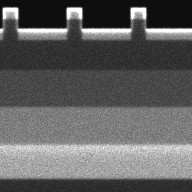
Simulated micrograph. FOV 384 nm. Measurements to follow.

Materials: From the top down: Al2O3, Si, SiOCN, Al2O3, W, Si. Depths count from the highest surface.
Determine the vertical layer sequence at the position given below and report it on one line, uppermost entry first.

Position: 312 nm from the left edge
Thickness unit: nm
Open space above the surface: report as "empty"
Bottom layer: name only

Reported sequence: empty 42, Al2O3 22, Si 60, SiOCN 74, Al2O3 76, W 68, Si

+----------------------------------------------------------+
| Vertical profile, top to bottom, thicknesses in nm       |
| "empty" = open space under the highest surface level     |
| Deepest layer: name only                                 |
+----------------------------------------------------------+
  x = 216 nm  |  empty 42, Al2O3 22, Si 60, SiOCN 74, Al2O3 76, W 68, Si